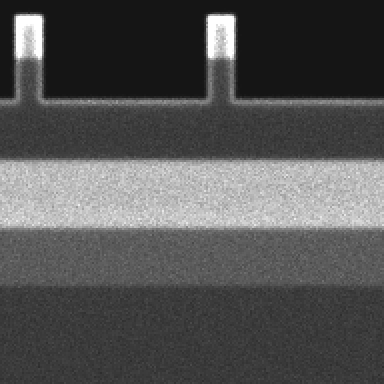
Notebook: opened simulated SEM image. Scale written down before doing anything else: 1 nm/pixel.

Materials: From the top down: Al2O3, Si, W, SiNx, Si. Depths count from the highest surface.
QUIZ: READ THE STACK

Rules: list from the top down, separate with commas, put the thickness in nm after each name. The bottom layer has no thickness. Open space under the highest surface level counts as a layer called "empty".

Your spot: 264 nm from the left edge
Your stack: empty 84, Si 60, W 68, SiNx 58, Si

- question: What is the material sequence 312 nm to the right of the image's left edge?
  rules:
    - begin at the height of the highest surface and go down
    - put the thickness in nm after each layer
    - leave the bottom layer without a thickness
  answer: empty 84, Si 60, W 68, SiNx 58, Si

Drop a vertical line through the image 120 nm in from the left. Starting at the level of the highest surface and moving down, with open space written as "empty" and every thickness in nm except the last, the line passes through empty 84, Si 60, W 68, SiNx 58, Si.